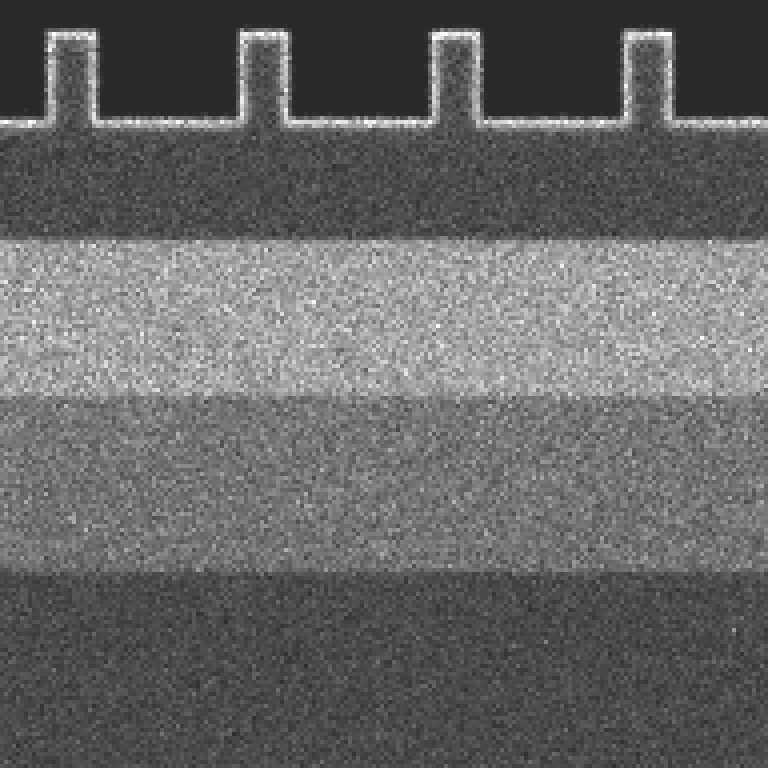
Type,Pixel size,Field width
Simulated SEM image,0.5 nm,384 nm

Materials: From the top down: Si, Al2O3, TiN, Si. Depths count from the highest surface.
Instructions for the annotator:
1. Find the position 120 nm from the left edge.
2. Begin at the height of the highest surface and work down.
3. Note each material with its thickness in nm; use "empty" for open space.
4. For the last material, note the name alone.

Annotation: Si 104, Al2O3 78, TiN 88, Si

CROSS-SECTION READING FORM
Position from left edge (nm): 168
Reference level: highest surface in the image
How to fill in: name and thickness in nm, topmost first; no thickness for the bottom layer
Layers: empty 44, Si 60, Al2O3 78, TiN 88, Si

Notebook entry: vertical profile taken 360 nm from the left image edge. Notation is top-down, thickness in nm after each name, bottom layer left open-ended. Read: empty 44, Si 60, Al2O3 78, TiN 88, Si